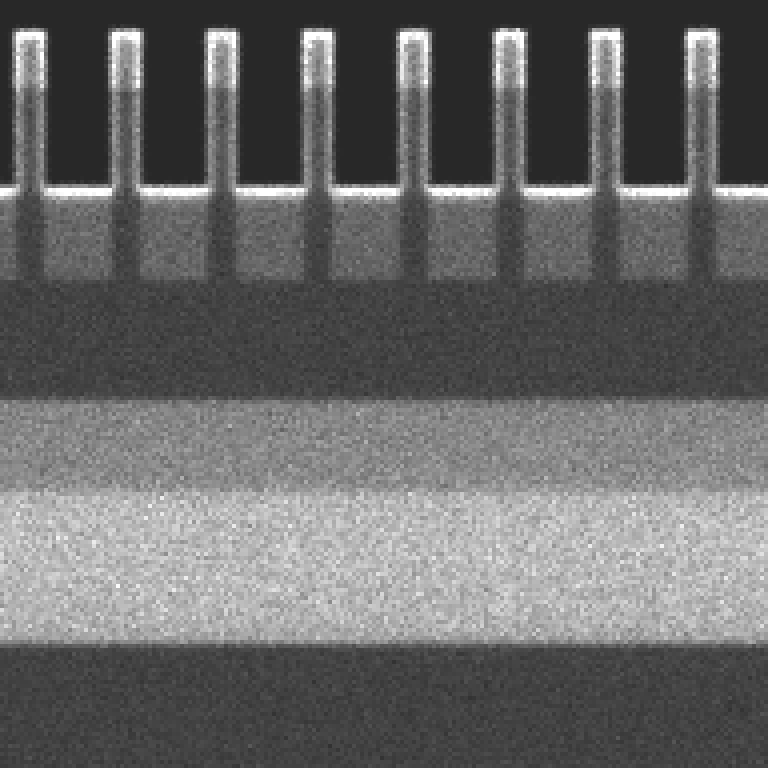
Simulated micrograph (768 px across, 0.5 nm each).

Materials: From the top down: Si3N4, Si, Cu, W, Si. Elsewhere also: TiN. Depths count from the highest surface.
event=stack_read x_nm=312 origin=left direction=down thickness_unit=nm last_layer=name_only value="empty 78, Si3N4 46, Si 60, Cu 46, W 76, Si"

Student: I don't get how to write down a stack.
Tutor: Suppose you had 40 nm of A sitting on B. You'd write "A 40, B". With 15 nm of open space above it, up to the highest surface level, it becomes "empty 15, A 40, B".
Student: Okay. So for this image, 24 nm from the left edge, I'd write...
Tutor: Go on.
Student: empty 78, Si3N4 46, Si 60, Cu 46, W 76, Si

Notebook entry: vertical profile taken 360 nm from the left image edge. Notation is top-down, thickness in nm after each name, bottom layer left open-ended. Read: empty 78, Si3N4 46, Si 60, Cu 46, W 76, Si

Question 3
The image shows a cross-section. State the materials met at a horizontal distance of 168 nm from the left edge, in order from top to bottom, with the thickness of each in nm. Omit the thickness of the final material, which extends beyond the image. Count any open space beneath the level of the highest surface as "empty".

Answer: empty 78, Si3N4 46, Si 60, Cu 46, W 76, Si